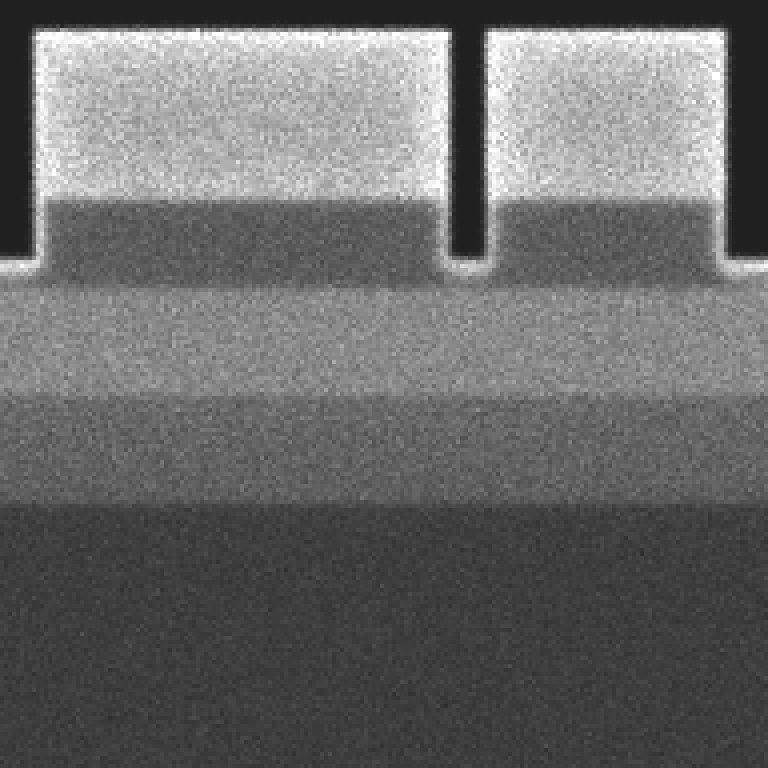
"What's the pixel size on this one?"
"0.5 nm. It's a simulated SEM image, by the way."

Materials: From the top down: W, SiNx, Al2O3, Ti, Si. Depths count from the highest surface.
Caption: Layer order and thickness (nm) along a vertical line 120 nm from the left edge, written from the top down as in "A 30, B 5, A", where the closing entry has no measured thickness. W 84, SiNx 44, Al2O3 54, Ti 54, Si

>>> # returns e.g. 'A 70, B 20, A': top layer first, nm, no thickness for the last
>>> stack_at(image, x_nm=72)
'W 84, SiNx 44, Al2O3 54, Ti 54, Si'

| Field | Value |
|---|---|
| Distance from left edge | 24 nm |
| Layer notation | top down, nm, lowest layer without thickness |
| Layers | W 84, SiNx 44, Al2O3 54, Ti 54, Si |